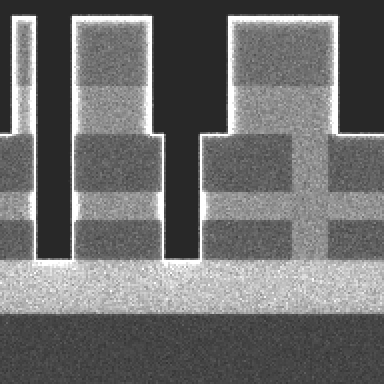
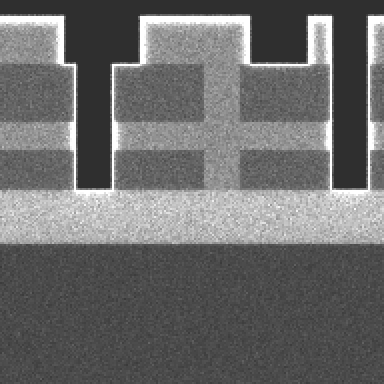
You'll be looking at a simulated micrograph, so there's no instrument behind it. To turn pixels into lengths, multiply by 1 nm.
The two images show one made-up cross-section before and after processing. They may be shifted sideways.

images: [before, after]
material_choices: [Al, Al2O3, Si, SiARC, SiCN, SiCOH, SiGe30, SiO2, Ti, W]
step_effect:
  removed: SiARC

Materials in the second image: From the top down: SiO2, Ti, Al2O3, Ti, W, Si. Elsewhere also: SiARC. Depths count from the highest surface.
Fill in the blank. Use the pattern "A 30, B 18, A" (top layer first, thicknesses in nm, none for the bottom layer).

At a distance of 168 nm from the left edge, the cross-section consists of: SiO2 48, Ti 58, Al2O3 28, Ti 40, W 54, Si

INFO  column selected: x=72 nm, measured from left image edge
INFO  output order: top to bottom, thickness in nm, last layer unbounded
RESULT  empty 48, Ti 58, Al2O3 28, Ti 40, W 54, Si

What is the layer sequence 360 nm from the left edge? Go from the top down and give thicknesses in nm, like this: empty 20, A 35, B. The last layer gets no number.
empty 174, W 54, Si